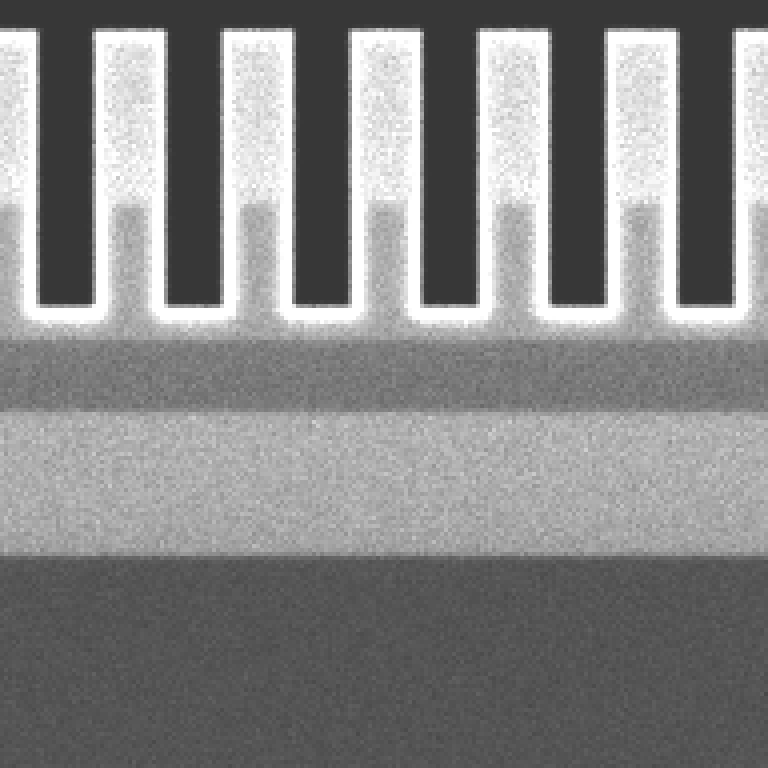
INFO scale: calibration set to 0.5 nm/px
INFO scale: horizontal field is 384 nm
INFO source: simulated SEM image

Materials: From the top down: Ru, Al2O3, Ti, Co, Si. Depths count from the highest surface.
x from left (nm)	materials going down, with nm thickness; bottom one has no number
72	Ru 86, Al2O3 68, Ti 36, Co 72, Si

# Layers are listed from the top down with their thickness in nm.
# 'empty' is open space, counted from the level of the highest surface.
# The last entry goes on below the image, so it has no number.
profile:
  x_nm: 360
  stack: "empty 138, Al2O3 16, Ti 36, Co 72, Si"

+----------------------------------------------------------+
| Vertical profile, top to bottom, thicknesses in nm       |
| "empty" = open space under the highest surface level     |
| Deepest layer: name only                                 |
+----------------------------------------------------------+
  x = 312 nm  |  Ru 86, Al2O3 68, Ti 36, Co 72, Si